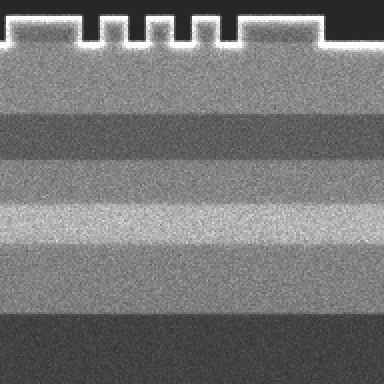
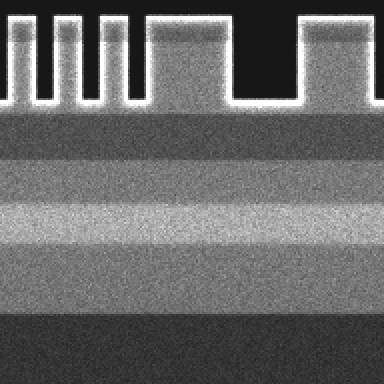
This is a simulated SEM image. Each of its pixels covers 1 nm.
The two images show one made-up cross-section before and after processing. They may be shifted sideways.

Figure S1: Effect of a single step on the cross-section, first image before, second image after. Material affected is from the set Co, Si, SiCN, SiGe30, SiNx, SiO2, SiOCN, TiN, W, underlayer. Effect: removed SiO2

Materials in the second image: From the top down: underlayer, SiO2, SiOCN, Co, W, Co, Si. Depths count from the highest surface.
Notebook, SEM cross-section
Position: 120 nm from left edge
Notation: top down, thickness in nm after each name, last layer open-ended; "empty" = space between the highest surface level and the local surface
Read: underlayer 26, SiO2 72, SiOCN 46, Co 44, W 40, Co 70, Si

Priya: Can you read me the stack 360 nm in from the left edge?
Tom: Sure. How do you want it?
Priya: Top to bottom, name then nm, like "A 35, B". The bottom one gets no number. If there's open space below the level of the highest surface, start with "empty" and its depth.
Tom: underlayer 26, SiO2 72, SiOCN 46, Co 44, W 40, Co 70, Si